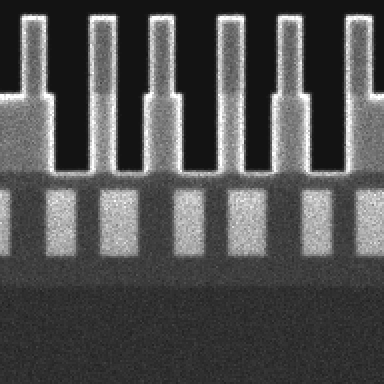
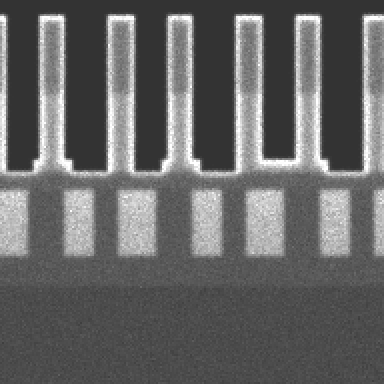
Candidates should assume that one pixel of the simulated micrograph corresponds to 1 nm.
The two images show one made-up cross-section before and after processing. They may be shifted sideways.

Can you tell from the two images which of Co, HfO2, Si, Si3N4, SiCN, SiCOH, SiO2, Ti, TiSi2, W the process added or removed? Yes, it removed SiO2.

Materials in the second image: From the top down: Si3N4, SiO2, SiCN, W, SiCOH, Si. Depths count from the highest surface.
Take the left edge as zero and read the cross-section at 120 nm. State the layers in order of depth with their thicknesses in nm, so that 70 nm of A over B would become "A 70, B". Si3N4 78, SiO2 78, SiCN 18, W 66, SiCOH 30, Si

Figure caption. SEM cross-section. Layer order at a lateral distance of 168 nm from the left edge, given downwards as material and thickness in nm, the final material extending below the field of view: Si3N4 78, SiO2 78, SiCN 18, SiCOH 96, Si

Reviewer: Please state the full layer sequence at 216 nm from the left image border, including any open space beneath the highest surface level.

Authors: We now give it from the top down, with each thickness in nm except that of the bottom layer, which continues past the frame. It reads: empty 156, SiCN 18, W 66, SiCOH 30, Si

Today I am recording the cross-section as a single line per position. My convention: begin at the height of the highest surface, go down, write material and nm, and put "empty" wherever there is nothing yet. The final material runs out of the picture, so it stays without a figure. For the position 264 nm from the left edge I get empty 144, SiO2 12, SiCN 18, W 66, SiCOH 30, Si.